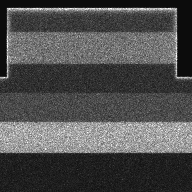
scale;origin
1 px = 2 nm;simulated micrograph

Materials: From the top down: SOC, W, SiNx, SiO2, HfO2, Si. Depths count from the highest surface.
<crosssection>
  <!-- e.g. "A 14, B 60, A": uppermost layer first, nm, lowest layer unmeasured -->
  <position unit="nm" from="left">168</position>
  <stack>SOC 48, W 64, SiNx 58, SiO2 58, HfO2 62, Si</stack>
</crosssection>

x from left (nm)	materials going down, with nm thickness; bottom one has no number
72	SOC 48, W 64, SiNx 58, SiO2 58, HfO2 62, Si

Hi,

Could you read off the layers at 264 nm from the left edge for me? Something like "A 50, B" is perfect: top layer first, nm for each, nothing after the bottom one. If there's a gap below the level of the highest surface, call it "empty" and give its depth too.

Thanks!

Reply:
SOC 48, W 64, SiNx 58, SiO2 58, HfO2 62, Si